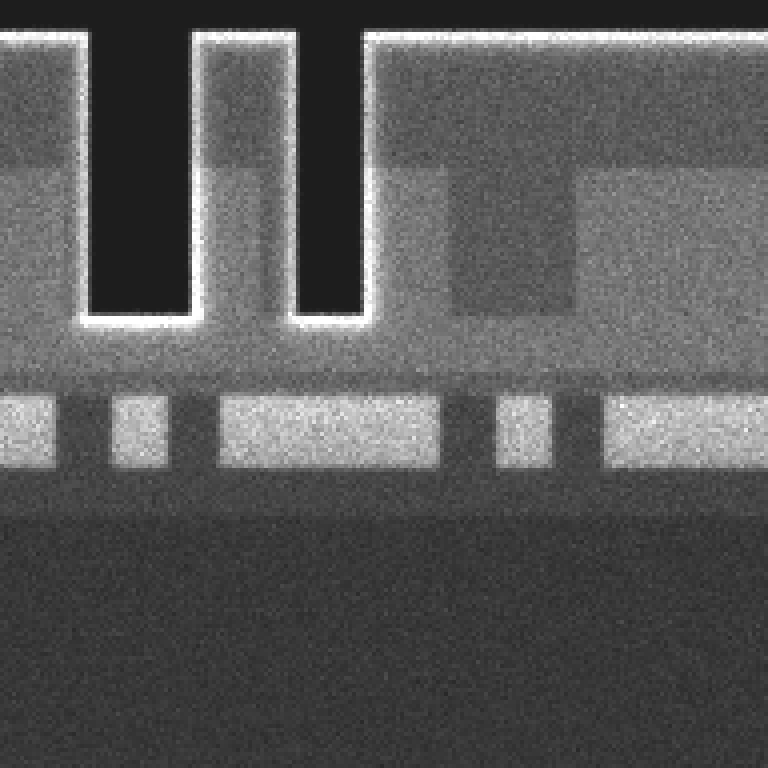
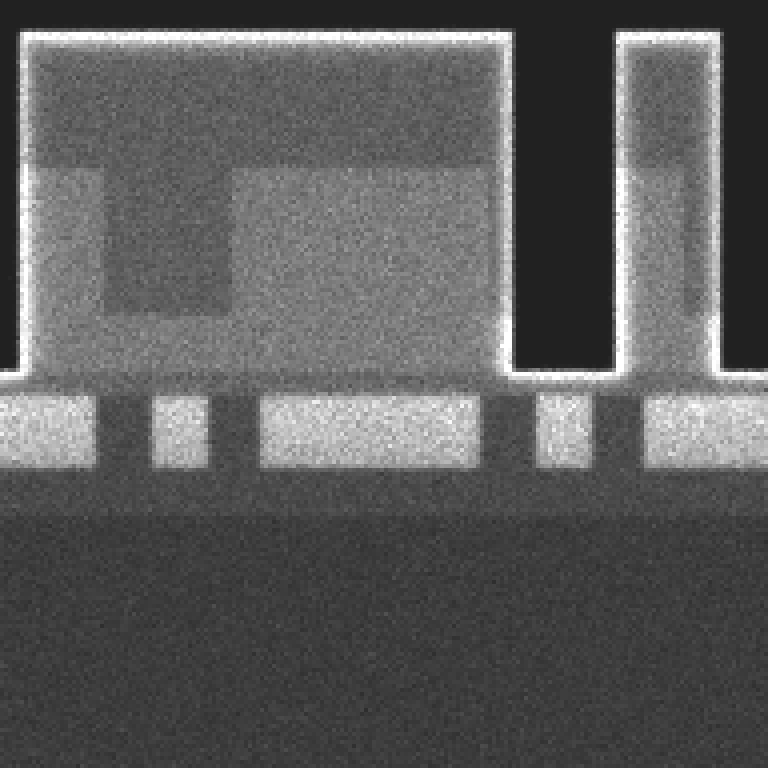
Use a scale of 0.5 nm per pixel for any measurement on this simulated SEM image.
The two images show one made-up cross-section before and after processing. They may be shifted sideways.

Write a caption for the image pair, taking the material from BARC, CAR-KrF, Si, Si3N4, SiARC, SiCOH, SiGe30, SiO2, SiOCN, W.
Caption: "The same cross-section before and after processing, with SiO2 removed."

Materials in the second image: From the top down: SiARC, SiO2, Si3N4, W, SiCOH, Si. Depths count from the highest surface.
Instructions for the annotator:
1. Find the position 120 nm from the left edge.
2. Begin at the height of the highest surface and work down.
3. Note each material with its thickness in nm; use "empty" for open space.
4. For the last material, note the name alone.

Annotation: SiARC 68, SiO2 102, Si3N4 12, SiCOH 60, Si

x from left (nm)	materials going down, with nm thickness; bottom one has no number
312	SiARC 68, SiO2 102, Si3N4 12, SiCOH 60, Si